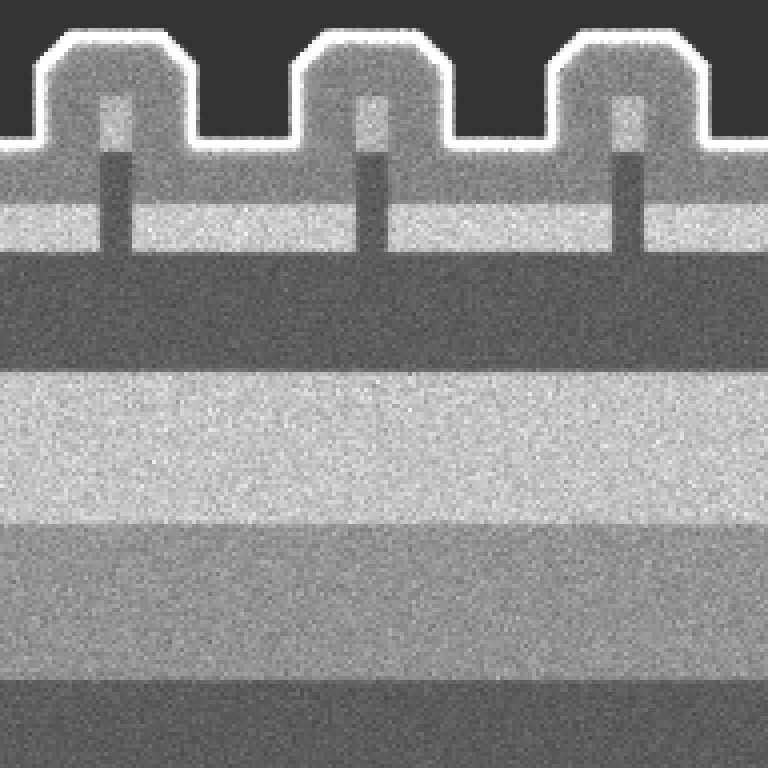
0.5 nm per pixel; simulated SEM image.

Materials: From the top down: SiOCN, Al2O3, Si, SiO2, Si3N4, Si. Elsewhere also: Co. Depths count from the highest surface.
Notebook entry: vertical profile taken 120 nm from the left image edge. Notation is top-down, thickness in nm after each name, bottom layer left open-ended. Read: empty 54, SiOCN 32, Al2O3 24, Si 60, SiO2 76, Si3N4 78, Si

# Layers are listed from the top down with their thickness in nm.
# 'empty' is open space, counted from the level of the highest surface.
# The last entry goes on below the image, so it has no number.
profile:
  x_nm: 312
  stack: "SiOCN 32, Co 28, Si 110, SiO2 76, Si3N4 78, Si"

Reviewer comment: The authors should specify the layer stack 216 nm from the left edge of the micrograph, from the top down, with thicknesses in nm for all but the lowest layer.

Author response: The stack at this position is empty 8, SiOCN 78, Al2O3 24, Si 60, SiO2 76, Si3N4 78, Si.